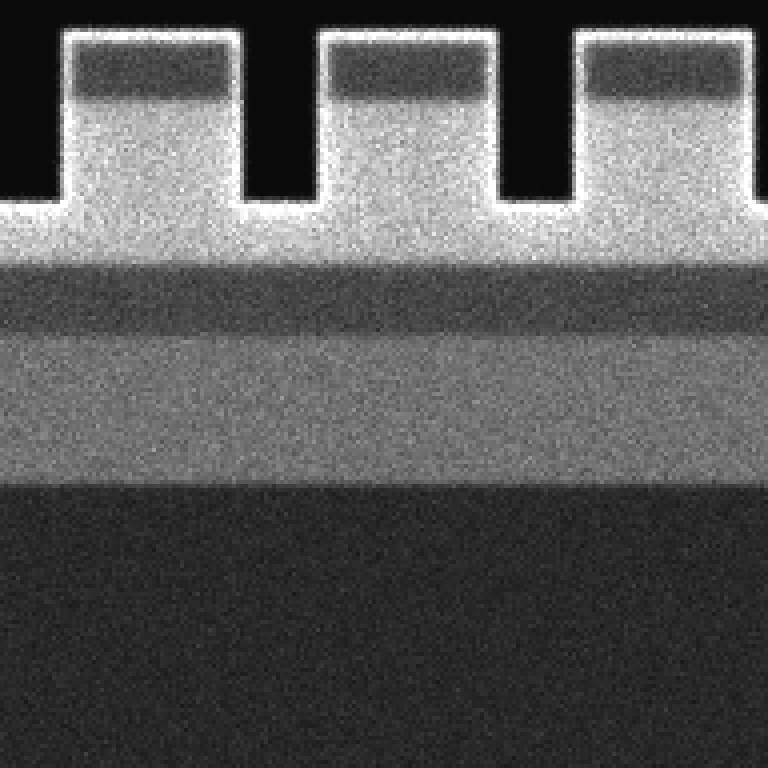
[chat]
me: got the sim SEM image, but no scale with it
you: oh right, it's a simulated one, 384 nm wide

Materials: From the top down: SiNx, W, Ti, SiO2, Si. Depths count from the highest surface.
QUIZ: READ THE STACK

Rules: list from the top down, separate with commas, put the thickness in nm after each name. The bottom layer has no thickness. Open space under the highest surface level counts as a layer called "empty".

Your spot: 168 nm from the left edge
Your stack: SiNx 34, W 82, Ti 36, SiO2 74, Si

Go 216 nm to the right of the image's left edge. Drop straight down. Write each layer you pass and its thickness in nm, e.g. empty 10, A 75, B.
SiNx 34, W 82, Ti 36, SiO2 74, Si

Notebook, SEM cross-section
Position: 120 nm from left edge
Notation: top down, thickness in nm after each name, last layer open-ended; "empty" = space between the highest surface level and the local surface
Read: empty 86, W 30, Ti 36, SiO2 74, Si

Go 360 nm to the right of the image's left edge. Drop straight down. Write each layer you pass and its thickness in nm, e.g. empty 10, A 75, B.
SiNx 34, W 82, Ti 36, SiO2 74, Si